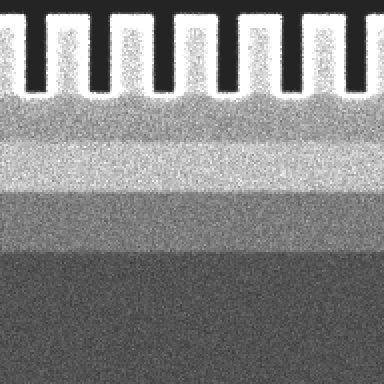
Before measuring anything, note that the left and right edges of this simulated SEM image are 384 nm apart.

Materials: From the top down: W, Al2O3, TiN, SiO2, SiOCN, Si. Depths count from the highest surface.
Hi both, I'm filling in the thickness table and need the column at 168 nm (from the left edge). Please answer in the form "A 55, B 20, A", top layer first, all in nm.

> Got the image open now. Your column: empty 78, TiN 48, SiO2 50, SiOCN 60, Si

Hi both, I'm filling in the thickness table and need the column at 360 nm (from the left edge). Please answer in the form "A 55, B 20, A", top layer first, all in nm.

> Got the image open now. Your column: empty 78, TiN 48, SiO2 50, SiOCN 60, Si